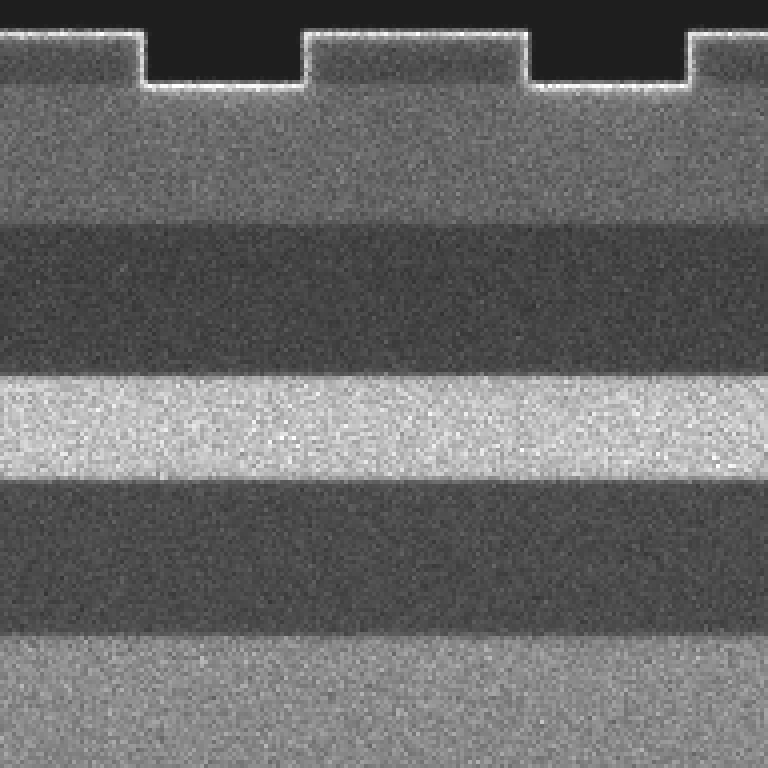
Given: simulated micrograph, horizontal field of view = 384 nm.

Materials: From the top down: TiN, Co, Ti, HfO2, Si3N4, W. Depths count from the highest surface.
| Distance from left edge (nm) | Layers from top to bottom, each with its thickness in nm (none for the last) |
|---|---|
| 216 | TiN 26, Co 70, Ti 76, HfO2 52, Si3N4 78, W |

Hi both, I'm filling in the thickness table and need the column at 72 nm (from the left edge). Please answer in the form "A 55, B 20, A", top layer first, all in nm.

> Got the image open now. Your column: empty 26, Co 70, Ti 76, HfO2 52, Si3N4 78, W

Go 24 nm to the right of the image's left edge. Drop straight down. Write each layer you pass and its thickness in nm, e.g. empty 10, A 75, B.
TiN 26, Co 70, Ti 76, HfO2 52, Si3N4 78, W